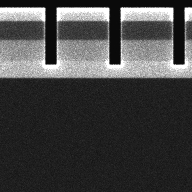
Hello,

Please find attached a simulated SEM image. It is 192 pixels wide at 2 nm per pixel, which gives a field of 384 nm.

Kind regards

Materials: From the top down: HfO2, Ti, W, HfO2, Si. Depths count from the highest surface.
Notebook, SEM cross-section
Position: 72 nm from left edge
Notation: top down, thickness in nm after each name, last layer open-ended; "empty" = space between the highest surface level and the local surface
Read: HfO2 26, Ti 38, W 42, HfO2 34, Si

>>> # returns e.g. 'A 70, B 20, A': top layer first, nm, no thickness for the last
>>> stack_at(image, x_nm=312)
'HfO2 26, Ti 38, W 42, HfO2 34, Si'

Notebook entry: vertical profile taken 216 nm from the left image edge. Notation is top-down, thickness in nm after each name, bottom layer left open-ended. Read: HfO2 26, Ti 38, W 42, HfO2 34, Si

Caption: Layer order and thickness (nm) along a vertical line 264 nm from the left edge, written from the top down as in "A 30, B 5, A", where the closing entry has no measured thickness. HfO2 26, Ti 38, W 42, HfO2 34, Si